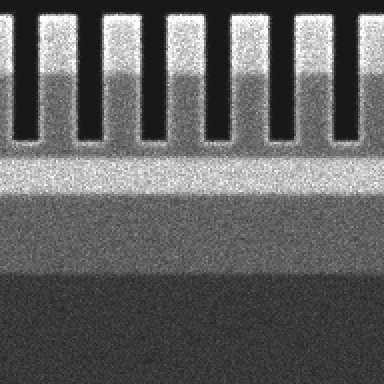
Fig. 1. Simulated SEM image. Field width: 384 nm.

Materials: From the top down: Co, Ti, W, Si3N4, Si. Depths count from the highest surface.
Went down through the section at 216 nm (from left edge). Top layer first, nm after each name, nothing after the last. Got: empty 126, Ti 16, W 36, Si3N4 80, Si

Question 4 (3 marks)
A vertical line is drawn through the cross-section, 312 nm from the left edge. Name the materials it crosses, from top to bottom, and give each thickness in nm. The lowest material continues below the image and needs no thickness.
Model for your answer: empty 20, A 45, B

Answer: Co 58, Ti 84, W 36, Si3N4 80, Si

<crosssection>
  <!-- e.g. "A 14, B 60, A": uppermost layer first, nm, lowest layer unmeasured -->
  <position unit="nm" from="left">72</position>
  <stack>Co 58, Ti 84, W 36, Si3N4 80, Si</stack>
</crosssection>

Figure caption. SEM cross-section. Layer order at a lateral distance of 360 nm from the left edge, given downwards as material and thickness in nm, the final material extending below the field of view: Co 58, Ti 84, W 36, Si3N4 80, Si